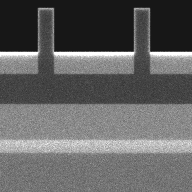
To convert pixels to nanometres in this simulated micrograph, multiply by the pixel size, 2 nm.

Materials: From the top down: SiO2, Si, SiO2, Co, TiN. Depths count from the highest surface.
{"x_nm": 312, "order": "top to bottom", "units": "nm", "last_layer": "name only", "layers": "empty 88, SiO2 44, Si 60, SiO2 72, Co 26, TiN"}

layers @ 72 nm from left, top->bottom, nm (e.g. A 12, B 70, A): empty 88, SiO2 44, Si 60, SiO2 72, Co 26, TiN